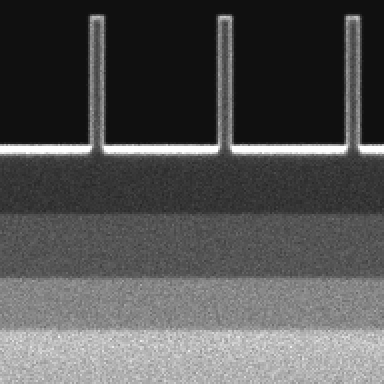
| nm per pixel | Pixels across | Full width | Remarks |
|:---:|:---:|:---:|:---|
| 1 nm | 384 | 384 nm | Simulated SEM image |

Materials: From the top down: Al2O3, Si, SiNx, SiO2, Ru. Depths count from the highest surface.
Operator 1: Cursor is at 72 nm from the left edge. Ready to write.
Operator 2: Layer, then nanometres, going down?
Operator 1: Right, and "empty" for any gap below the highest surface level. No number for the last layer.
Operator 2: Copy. empty 130, Al2O3 8, Si 60, SiNx 64, SiO2 52, Ru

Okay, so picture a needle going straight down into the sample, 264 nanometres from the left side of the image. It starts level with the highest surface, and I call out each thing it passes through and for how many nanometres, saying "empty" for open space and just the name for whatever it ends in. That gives empty 130, Al2O3 8, Si 60, SiNx 64, SiO2 52, Ru